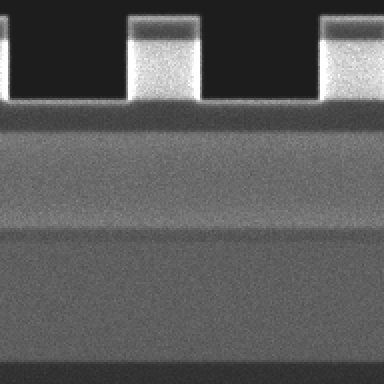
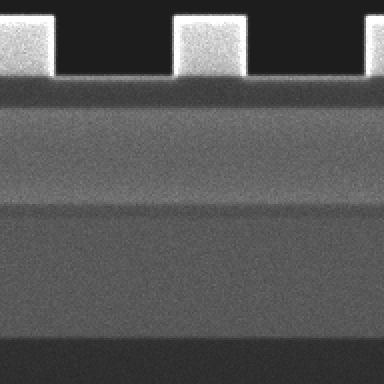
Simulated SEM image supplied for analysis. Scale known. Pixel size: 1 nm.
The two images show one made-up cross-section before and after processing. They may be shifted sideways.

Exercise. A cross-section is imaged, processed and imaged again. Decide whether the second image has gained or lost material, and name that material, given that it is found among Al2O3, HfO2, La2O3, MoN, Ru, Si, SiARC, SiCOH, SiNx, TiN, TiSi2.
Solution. removed: SiARC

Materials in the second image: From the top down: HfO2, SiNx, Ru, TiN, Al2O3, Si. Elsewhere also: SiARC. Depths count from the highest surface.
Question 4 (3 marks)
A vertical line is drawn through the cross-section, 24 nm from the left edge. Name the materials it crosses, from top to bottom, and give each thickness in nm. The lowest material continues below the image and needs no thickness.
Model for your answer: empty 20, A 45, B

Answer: HfO2 60, SiNx 32, Ru 96, TiN 14, Al2O3 120, Si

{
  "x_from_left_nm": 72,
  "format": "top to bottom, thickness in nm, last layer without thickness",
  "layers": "empty 60, SiNx 32, Ru 96, TiN 14, Al2O3 120, Si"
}